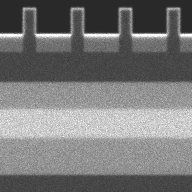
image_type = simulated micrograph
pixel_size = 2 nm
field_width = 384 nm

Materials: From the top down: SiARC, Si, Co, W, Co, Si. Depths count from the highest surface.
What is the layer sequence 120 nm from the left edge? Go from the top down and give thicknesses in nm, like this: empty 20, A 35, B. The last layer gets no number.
empty 52, SiARC 36, Si 60, Co 54, W 58, Co 74, Si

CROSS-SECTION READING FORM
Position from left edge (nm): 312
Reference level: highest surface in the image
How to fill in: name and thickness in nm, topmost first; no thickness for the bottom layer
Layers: empty 52, SiARC 36, Si 60, Co 54, W 58, Co 74, Si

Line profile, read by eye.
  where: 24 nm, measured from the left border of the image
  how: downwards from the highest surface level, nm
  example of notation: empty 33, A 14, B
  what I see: empty 52, SiARC 36, Si 60, Co 54, W 58, Co 74, Si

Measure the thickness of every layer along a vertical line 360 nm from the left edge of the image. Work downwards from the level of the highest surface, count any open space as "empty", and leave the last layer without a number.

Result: empty 52, SiARC 36, Si 60, Co 54, W 58, Co 74, Si